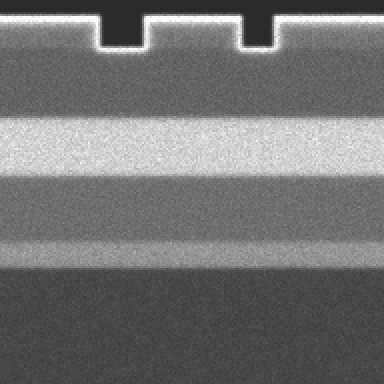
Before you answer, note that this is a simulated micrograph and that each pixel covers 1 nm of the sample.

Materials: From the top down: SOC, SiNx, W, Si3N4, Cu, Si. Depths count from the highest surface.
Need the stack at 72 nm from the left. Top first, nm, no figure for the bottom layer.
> SOC 32, SiNx 70, W 58, Si3N4 66, Cu 26, Si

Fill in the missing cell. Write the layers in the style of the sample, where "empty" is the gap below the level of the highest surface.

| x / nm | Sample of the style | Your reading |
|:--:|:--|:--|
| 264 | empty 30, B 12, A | empty 32, SiNx 70, W 58, Si3N4 66, Cu 26, Si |